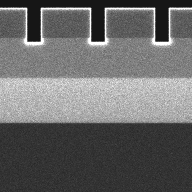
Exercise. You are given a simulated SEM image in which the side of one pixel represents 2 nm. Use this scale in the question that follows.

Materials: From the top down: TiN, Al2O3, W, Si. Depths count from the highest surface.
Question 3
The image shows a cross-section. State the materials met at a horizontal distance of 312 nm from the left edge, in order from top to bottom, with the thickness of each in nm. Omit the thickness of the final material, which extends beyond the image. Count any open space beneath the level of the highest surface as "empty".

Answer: empty 68, Al2O3 72, W 90, Si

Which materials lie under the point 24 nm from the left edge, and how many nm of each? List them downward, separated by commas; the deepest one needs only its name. TiN 60, Al2O3 80, W 90, Si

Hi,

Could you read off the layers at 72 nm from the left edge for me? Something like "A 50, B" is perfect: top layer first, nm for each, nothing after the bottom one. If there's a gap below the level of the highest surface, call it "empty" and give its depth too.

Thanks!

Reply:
empty 68, Al2O3 72, W 90, Si